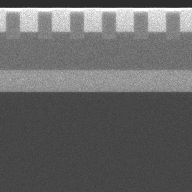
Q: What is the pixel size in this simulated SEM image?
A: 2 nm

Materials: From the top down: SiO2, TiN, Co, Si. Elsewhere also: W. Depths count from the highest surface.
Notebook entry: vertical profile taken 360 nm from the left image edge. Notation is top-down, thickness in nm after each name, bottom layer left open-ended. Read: W 48, TiN 76, Co 44, Si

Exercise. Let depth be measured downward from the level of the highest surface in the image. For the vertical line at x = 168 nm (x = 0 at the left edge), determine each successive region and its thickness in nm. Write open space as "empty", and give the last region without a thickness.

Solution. W 48, TiN 76, Co 44, Si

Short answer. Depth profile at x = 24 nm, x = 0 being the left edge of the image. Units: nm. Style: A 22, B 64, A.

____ SiO2 62, TiN 62, Co 44, Si